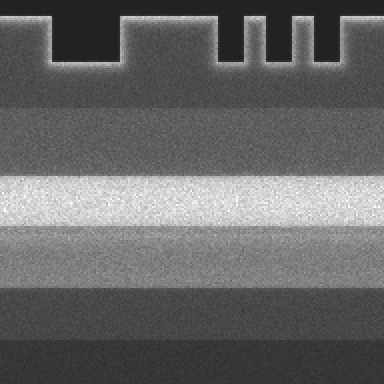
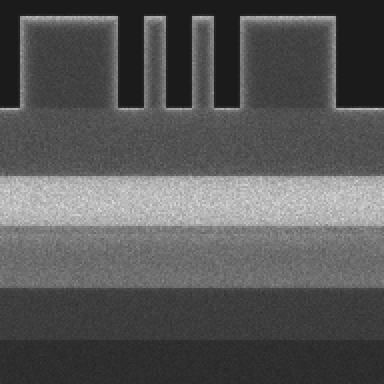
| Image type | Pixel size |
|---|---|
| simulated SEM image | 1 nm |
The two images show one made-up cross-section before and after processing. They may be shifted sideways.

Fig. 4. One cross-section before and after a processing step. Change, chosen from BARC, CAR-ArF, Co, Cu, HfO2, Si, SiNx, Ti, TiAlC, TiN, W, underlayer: underlayer removed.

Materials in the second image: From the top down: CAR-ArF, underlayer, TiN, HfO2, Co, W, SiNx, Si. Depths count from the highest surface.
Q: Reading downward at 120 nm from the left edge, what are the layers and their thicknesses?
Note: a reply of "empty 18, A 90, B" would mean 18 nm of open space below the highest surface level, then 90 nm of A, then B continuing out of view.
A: empty 92, TiN 68, HfO2 50, Co 8, W 54, SiNx 52, Si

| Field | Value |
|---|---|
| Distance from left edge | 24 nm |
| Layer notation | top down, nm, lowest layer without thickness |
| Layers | CAR-ArF 46, underlayer 46, TiN 68, HfO2 50, Co 8, W 54, SiNx 52, Si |